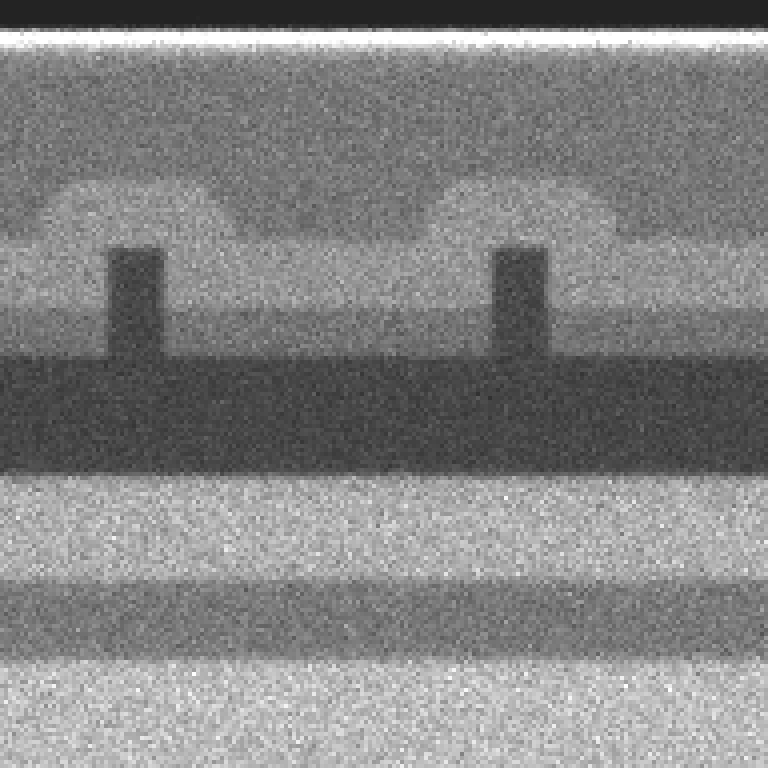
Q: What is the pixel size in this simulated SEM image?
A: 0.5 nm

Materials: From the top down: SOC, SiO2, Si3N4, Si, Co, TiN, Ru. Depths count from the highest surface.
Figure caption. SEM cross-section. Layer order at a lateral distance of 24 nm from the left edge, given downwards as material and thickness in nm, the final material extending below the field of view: SOC 86, SiO2 52, Si3N4 24, Si 60, Co 52, TiN 40, Ru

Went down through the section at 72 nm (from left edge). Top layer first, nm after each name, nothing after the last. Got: SOC 74, SiO2 34, Si 114, Co 52, TiN 40, Ru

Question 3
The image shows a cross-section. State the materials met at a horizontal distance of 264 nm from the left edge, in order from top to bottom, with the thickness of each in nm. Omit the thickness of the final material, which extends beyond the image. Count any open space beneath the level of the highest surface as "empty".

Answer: SOC 74, SiO2 34, Si 114, Co 52, TiN 40, Ru